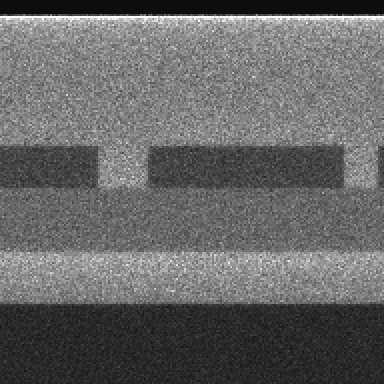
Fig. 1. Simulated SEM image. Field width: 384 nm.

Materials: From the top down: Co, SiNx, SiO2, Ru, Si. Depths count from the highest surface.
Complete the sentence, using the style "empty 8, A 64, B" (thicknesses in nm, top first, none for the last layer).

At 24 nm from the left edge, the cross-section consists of Co 130, SiNx 42, SiO2 64, Ru 52, Si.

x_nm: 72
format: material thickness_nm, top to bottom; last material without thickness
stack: Co 130, SiNx 42, SiO2 64, Ru 52, Si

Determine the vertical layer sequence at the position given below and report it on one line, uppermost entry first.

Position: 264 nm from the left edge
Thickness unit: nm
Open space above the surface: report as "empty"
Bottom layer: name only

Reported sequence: Co 130, SiNx 42, SiO2 64, Ru 52, Si